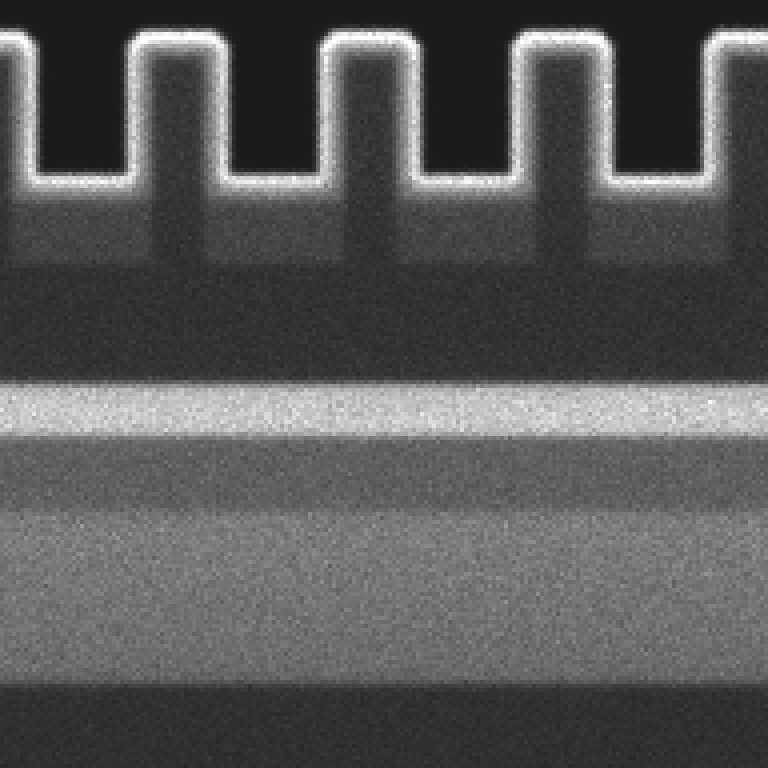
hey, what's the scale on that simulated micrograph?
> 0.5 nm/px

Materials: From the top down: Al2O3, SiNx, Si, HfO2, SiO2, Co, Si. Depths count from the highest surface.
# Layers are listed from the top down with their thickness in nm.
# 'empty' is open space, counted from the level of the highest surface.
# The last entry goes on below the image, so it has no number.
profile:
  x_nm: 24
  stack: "empty 72, Al2O3 12, SiNx 32, Si 60, HfO2 26, SiO2 38, Co 86, Si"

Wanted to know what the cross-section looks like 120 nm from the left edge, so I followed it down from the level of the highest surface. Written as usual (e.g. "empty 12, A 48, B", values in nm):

empty 72, Al2O3 12, SiNx 32, Si 60, HfO2 26, SiO2 38, Co 86, Si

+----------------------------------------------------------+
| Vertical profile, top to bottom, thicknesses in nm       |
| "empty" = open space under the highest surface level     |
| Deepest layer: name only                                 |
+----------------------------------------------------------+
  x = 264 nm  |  Al2O3 84, SiNx 32, Si 60, HfO2 26, SiO2 38, Co 86, Si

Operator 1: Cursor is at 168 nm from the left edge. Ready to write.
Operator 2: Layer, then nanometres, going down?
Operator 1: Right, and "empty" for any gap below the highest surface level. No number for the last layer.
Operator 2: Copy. Al2O3 84, SiNx 32, Si 60, HfO2 26, SiO2 38, Co 86, Si